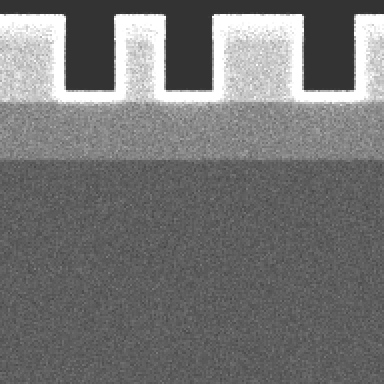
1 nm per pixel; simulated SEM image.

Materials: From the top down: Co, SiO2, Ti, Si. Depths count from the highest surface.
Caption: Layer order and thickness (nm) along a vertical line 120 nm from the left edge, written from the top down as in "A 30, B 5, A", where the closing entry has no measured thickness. Co 24, SiO2 62, Ti 58, Si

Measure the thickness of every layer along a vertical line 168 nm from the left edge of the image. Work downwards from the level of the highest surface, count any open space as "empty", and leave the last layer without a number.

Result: empty 76, SiO2 10, Ti 58, Si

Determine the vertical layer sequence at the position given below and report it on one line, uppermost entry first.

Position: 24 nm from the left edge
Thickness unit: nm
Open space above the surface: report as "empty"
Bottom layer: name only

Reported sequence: Co 24, SiO2 62, Ti 58, Si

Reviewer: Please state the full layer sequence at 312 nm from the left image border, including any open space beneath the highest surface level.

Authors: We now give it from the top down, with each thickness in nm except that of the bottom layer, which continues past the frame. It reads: empty 76, SiO2 10, Ti 58, Si